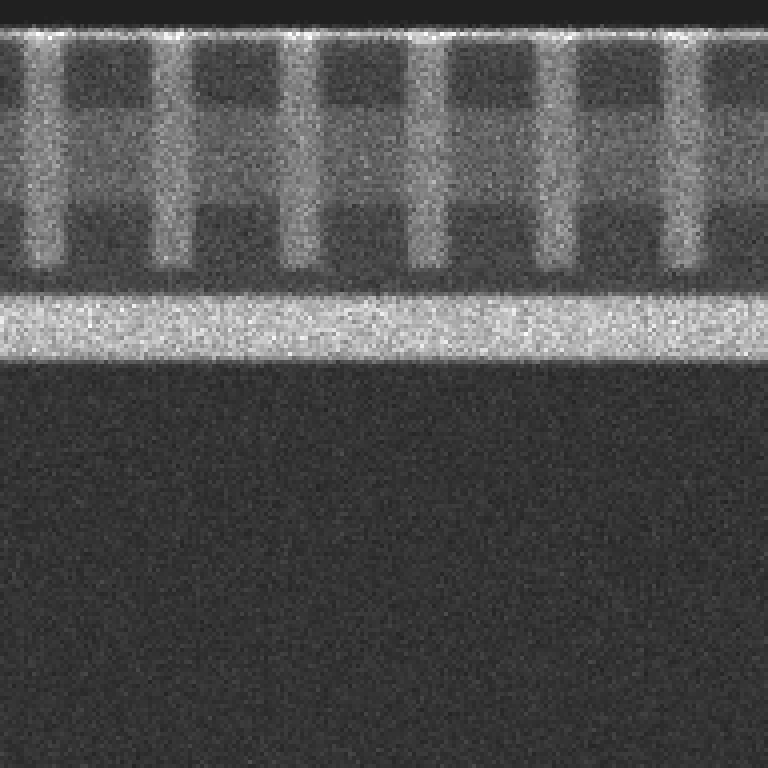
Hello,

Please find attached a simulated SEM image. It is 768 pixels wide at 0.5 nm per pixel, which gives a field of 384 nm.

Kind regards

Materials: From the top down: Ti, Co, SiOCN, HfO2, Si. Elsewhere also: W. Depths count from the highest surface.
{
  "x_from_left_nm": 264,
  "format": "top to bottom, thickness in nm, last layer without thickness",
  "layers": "Ti 38, Co 48, SiOCN 46, HfO2 32, Si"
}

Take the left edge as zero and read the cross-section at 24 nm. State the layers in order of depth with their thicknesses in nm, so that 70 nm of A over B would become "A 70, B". W 118, SiOCN 14, HfO2 32, Si